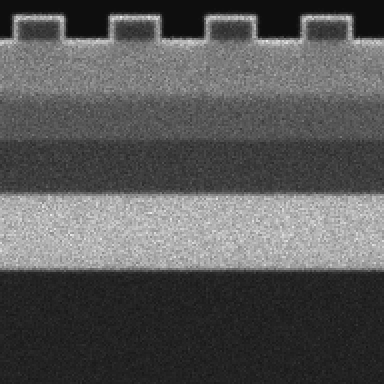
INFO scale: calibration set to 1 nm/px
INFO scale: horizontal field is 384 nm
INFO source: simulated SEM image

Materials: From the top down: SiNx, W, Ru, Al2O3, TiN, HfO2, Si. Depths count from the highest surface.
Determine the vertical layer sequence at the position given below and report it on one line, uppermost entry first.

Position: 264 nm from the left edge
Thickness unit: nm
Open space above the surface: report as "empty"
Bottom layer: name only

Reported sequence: empty 24, W 54, Ru 8, Al2O3 38, TiN 54, HfO2 76, Si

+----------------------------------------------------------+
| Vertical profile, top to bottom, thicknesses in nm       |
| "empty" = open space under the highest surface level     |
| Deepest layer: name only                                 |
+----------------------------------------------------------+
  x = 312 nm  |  SiNx 24, W 54, Ru 8, Al2O3 38, TiN 54, HfO2 76, Si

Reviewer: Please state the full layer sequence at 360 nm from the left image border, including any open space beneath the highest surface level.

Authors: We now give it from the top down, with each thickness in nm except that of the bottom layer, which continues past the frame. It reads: empty 24, W 54, Ru 8, Al2O3 38, TiN 54, HfO2 76, Si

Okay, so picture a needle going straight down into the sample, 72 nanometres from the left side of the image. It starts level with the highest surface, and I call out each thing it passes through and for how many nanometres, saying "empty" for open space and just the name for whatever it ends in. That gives empty 24, W 54, Ru 8, Al2O3 38, TiN 54, HfO2 76, Si